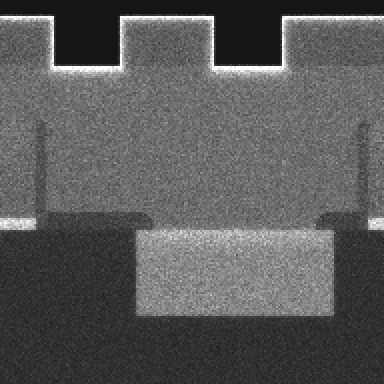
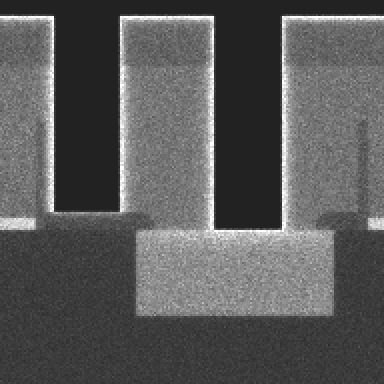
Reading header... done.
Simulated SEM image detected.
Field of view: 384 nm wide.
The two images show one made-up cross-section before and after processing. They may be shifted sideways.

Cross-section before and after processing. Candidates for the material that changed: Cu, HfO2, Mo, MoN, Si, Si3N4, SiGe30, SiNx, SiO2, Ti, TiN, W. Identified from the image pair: SiO2 (removed).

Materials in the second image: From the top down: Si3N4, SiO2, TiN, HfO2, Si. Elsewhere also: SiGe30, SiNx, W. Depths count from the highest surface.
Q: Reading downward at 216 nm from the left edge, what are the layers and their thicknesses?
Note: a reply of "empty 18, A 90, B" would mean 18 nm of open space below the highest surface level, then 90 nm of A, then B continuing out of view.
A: empty 214, W 86, Si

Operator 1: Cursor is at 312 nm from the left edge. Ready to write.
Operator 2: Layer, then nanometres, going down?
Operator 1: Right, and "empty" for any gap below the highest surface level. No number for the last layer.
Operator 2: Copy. Si3N4 50, SiO2 164, W 86, Si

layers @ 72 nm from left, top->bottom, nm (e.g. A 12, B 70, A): empty 196, SiGe30 18, Si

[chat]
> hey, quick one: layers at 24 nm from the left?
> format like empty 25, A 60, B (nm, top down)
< Si3N4 50, SiO2 54, TiN 98, HfO2 12, Si